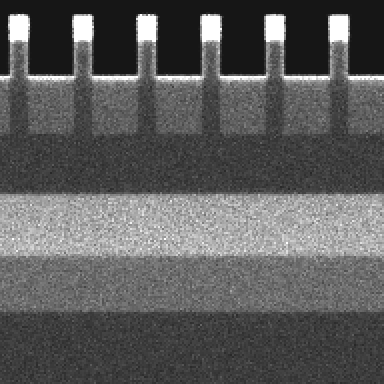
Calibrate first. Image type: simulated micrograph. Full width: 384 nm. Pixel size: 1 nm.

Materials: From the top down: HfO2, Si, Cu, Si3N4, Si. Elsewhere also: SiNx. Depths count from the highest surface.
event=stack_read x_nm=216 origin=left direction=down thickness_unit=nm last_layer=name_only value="HfO2 24, Si 154, Cu 62, Si3N4 56, Si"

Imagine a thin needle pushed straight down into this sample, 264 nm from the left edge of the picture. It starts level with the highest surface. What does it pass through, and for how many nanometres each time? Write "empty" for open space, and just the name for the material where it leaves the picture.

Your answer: empty 60, SiNx 58, Si 60, Cu 62, Si3N4 56, Si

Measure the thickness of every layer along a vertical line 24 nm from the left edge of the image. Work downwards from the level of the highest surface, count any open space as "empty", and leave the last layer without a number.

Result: HfO2 24, Si 154, Cu 62, Si3N4 56, Si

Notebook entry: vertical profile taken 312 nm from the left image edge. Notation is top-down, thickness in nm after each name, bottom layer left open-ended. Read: empty 60, SiNx 58, Si 60, Cu 62, Si3N4 56, Si